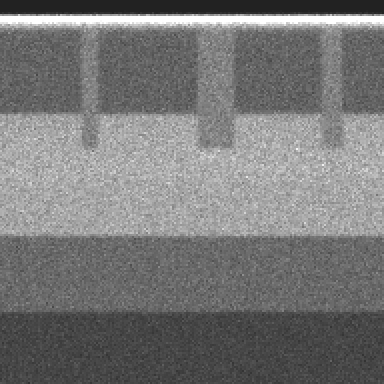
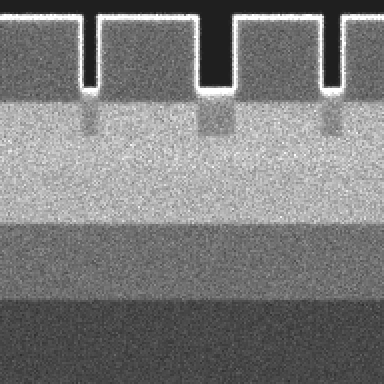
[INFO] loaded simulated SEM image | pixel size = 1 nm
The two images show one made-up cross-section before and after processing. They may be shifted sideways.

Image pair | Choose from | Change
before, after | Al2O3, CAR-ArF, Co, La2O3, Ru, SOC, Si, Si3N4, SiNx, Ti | SOC (removed)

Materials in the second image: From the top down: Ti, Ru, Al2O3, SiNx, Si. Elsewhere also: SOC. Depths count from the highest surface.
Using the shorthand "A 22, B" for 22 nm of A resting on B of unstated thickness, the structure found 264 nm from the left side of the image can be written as Ti 86, Ru 68, Al2O3 54, SiNx 76, Si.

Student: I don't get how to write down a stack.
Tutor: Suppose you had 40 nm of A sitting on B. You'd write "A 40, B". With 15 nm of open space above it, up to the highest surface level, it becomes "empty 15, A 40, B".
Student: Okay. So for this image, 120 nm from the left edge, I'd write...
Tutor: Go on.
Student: Ti 86, Ru 68, Al2O3 54, SiNx 76, Si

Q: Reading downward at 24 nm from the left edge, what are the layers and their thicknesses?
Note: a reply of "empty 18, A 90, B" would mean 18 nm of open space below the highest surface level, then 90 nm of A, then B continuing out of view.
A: Ti 86, Ru 68, Al2O3 54, SiNx 76, Si